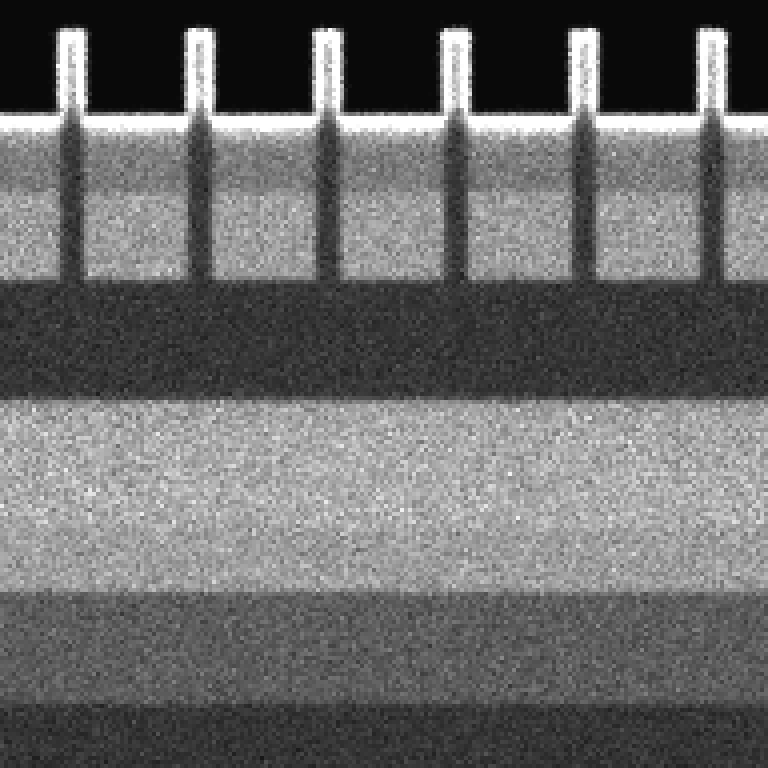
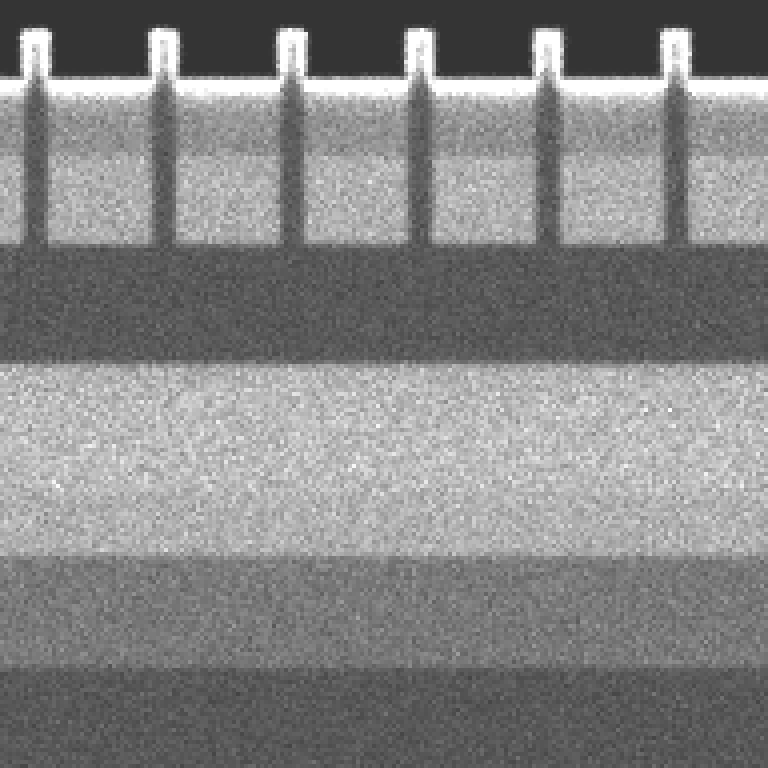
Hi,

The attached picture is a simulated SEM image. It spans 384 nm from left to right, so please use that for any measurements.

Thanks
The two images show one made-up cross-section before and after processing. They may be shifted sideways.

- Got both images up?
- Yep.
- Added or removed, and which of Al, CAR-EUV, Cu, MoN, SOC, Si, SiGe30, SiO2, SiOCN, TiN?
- removed, TiN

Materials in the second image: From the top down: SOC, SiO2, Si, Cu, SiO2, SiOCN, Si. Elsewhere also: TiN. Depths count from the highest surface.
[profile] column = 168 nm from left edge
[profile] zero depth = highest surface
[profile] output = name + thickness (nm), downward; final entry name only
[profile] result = empty 24, SOC 38, SiO2 44, Si 60, Cu 64, SiO2 32, SiOCN 56, Si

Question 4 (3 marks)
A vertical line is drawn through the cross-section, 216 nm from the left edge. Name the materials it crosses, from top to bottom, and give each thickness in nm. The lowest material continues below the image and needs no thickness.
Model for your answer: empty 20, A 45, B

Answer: empty 24, SOC 38, SiO2 44, Si 60, Cu 64, SiO2 32, SiOCN 56, Si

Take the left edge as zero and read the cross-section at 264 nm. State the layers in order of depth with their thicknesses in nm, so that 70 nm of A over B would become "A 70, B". empty 24, SOC 38, SiO2 44, Si 60, Cu 64, SiO2 32, SiOCN 56, Si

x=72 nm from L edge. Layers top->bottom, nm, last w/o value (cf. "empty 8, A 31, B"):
empty 24, SOC 38, SiO2 44, Si 60, Cu 64, SiO2 32, SiOCN 56, Si